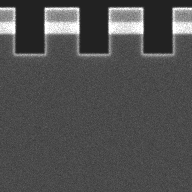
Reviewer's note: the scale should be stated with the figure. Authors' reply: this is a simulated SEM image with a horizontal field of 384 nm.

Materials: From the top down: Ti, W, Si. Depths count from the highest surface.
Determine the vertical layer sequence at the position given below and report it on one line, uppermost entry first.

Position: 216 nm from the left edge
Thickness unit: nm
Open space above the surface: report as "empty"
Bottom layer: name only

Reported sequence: empty 92, Si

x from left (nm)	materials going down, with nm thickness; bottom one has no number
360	Ti 28, W 24, Si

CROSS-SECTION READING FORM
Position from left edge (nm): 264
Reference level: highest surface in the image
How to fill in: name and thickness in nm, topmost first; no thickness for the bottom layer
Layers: Ti 28, W 24, Si